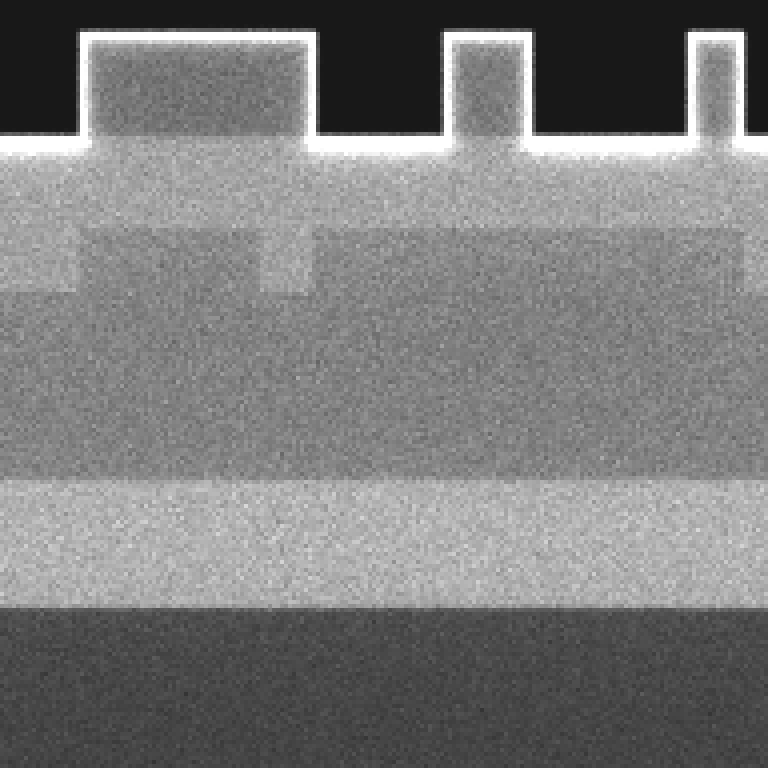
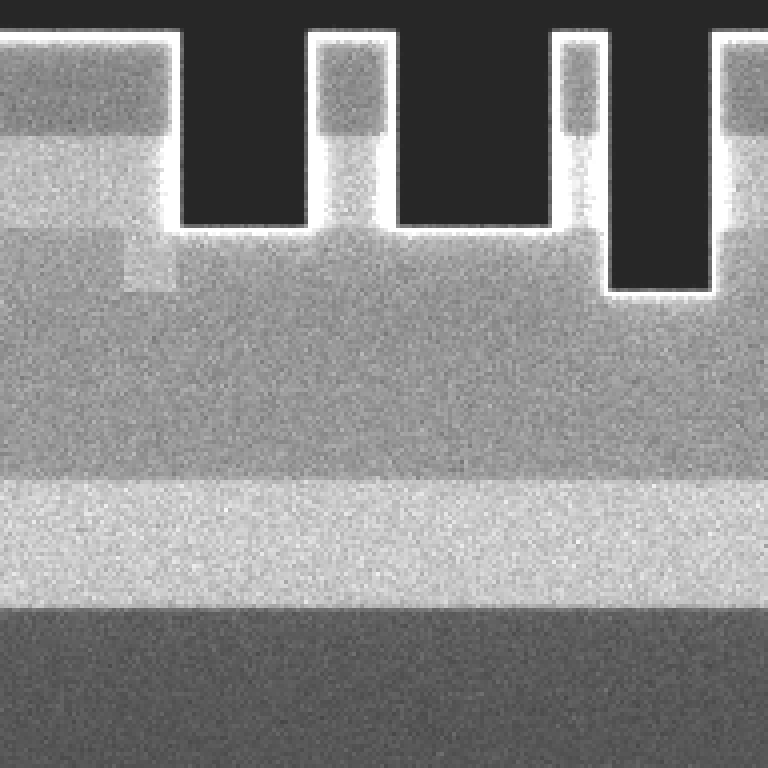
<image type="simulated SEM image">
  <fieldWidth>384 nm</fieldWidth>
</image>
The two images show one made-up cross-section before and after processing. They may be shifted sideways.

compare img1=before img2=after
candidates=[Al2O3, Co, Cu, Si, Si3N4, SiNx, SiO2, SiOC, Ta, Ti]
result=removed:SiO2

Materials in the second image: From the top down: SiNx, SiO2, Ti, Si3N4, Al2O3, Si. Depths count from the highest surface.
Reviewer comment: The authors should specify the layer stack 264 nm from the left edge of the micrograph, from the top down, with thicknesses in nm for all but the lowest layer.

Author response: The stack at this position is empty 98, Ti 78, Si3N4 48, Al2O3 64, Si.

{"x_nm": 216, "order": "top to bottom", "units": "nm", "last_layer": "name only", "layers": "empty 98, Ti 78, Si3N4 48, Al2O3 64, Si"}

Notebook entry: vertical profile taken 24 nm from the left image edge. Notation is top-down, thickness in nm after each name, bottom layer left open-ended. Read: SiNx 52, SiO2 46, Ti 78, Si3N4 48, Al2O3 64, Si